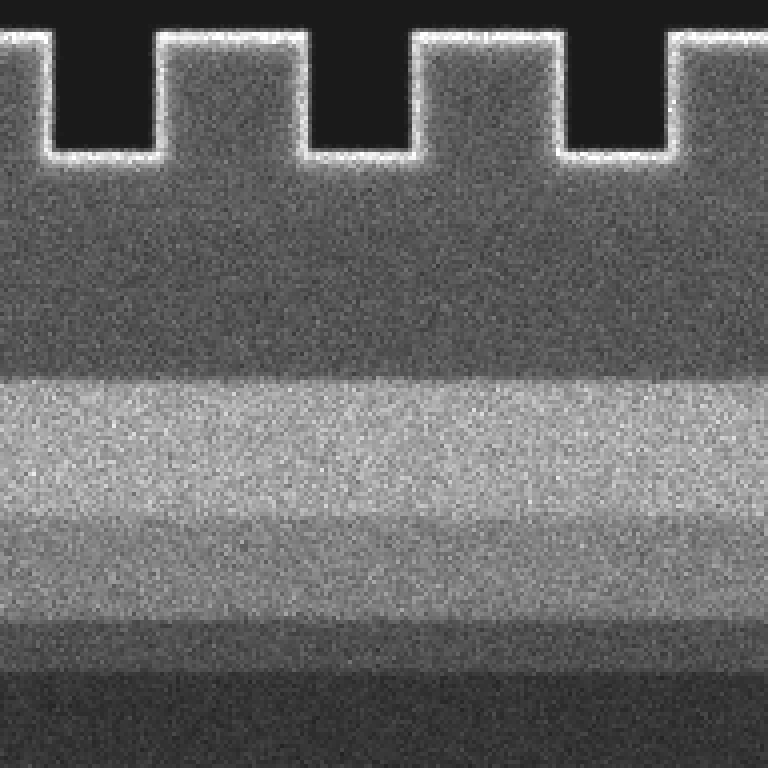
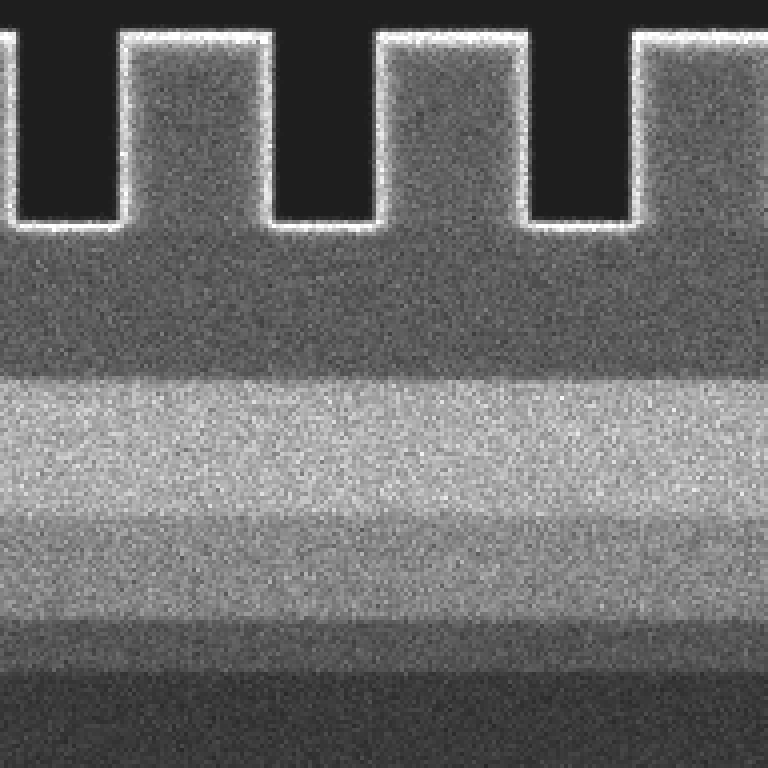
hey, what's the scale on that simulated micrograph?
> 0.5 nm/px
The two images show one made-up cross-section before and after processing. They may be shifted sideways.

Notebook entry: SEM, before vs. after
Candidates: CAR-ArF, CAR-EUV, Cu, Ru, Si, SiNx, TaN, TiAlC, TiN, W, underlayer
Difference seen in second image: underlayer removed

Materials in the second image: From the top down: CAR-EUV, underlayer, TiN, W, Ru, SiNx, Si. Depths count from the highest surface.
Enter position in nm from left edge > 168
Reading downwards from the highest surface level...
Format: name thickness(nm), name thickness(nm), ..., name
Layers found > empty 96, TiN 78, W 68, Ru 52, SiNx 26, Si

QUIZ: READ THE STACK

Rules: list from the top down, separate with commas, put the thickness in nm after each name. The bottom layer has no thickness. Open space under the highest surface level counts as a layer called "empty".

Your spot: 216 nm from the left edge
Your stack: CAR-EUV 60, underlayer 36, TiN 78, W 68, Ru 52, SiNx 26, Si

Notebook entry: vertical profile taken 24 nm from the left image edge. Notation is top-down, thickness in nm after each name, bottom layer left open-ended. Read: empty 96, TiN 78, W 68, Ru 52, SiNx 26, Si